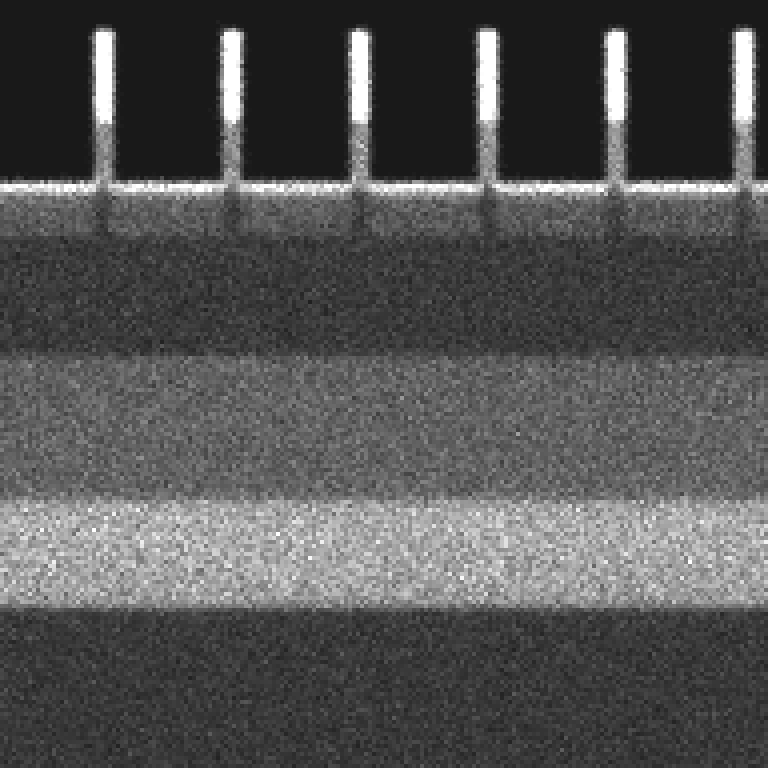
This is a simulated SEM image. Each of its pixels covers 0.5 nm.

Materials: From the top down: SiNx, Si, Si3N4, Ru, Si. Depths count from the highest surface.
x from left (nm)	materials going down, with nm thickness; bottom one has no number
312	empty 76, SiNx 26, Si 60, Si3N4 72, Ru 54, Si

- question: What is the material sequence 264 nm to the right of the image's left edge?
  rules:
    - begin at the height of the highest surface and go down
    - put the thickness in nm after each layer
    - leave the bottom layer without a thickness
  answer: empty 76, SiNx 26, Si 60, Si3N4 72, Ru 54, Si